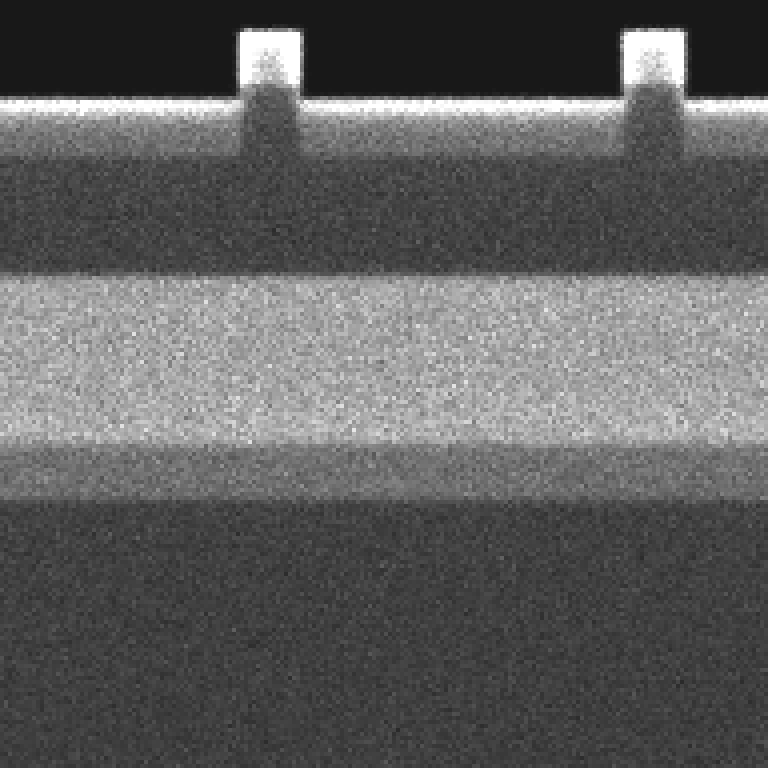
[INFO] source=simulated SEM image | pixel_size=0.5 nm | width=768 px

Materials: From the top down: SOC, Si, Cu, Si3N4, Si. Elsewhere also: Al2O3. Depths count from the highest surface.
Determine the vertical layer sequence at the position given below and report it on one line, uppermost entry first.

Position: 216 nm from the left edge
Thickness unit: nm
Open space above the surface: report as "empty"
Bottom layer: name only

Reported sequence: empty 34, SOC 28, Si 60, Cu 84, Si3N4 28, Si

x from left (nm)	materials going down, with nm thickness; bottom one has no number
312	Al2O3 26, Si 96, Cu 84, Si3N4 28, Si